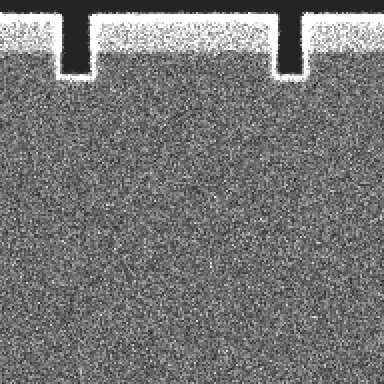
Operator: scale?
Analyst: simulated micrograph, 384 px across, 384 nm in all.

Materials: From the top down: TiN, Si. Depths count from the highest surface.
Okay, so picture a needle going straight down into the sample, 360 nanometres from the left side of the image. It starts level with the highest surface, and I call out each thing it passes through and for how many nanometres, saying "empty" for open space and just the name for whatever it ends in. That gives TiN 36, Si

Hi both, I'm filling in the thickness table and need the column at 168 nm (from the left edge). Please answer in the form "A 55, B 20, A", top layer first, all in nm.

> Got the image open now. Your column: TiN 36, Si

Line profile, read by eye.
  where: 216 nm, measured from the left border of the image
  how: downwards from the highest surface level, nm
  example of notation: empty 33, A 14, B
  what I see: TiN 36, Si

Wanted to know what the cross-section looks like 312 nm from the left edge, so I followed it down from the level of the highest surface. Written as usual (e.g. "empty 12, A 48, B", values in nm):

TiN 36, Si